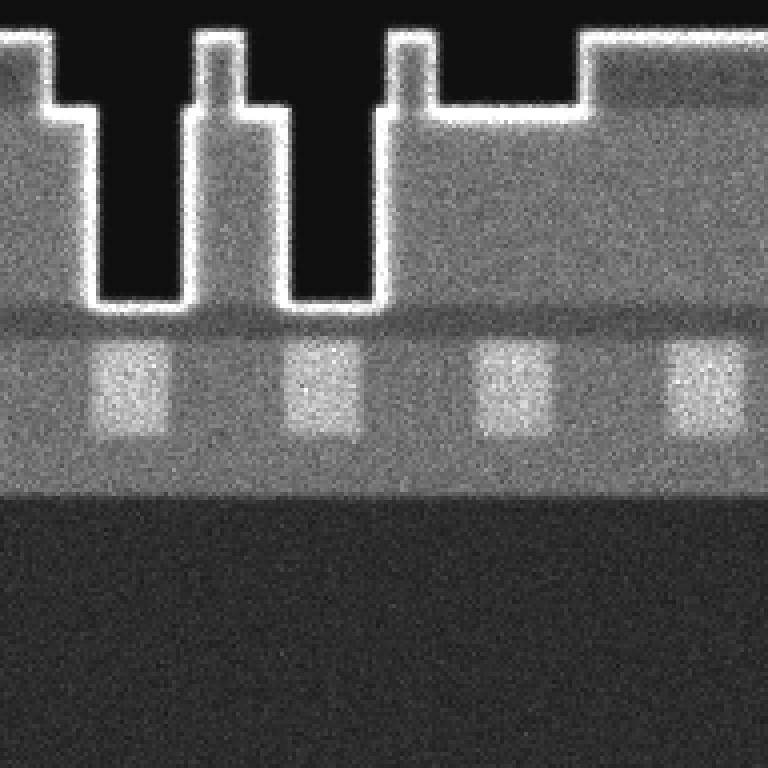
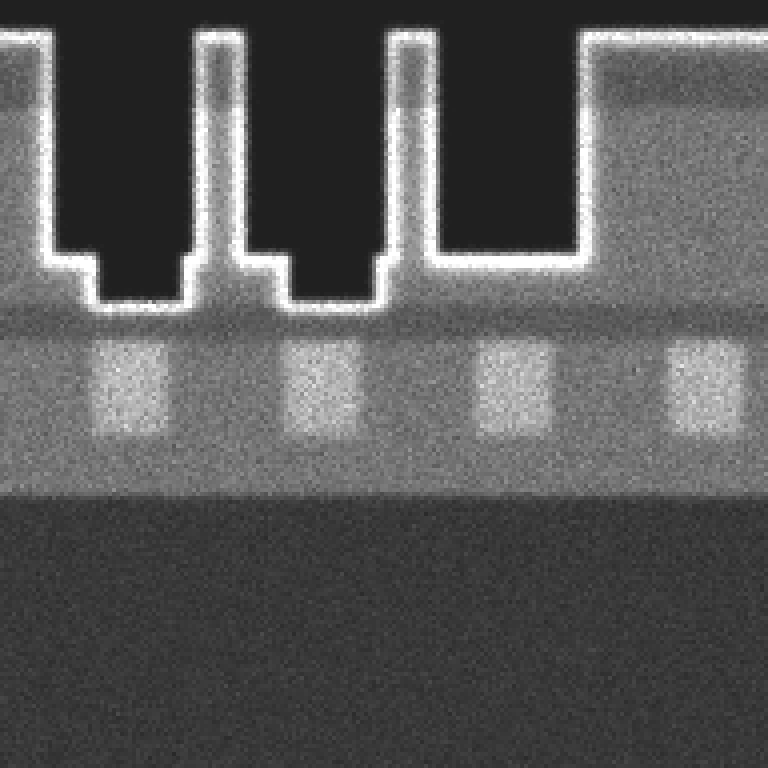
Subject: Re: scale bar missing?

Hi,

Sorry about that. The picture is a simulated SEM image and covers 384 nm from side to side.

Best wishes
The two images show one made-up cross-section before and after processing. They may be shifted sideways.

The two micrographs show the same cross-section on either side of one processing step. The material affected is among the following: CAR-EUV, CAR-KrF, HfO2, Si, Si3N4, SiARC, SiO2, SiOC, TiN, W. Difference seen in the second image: SiO2 removed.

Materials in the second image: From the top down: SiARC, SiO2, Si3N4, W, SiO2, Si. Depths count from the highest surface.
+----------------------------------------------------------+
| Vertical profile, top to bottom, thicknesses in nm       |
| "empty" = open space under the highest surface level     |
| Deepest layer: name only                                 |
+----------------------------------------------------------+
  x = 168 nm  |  empty 136, Si3N4 18, W 48, SiO2 30, Si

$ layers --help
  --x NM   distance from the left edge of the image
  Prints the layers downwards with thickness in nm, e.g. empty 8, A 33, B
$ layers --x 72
empty 136, Si3N4 18, W 48, SiO2 30, Si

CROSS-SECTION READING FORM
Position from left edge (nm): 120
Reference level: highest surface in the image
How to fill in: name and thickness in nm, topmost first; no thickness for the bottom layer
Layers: SiARC 38, SiO2 98, Si3N4 18, SiO2 78, Si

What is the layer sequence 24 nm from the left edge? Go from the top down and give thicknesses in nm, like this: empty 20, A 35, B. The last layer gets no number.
SiARC 38, SiO2 98, Si3N4 18, SiO2 78, Si